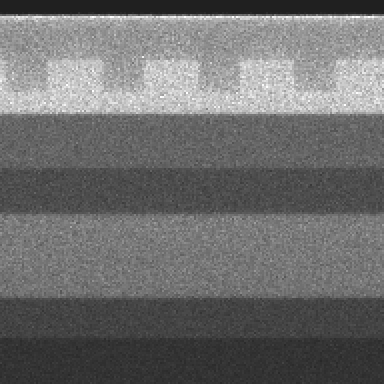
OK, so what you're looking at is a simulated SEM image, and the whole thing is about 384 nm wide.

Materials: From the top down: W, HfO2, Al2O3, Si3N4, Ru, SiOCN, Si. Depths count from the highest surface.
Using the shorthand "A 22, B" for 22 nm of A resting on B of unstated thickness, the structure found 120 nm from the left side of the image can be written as W 76, HfO2 22, Al2O3 54, Si3N4 46, Ru 84, SiOCN 40, Si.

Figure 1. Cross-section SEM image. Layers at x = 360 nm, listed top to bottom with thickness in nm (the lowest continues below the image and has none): W 44, HfO2 54, Al2O3 54, Si3N4 46, Ru 84, SiOCN 40, Si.